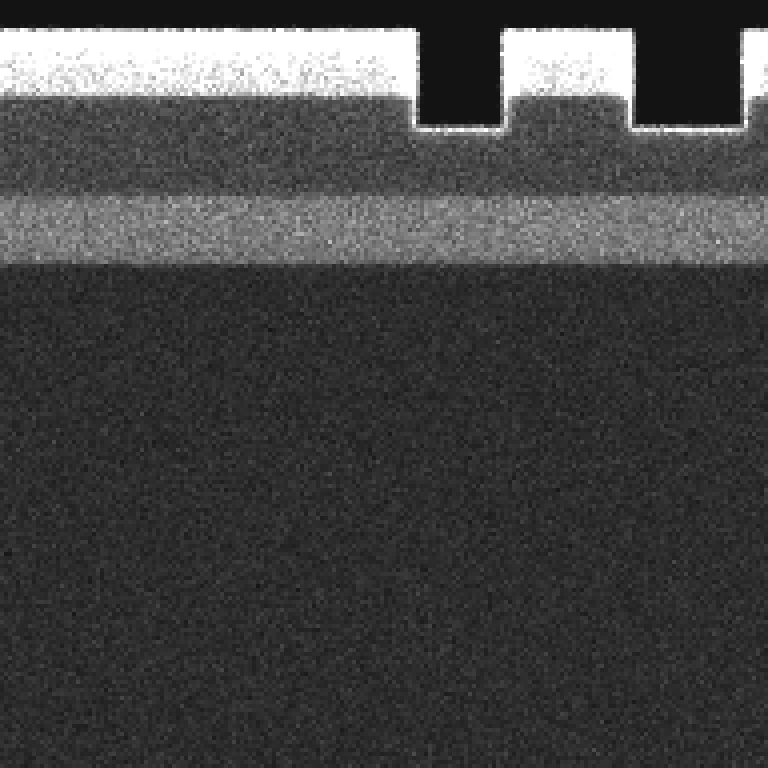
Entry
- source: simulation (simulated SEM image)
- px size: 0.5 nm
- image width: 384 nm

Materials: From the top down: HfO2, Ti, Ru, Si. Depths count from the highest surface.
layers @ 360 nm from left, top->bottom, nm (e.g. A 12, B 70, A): empty 48, Ti 34, Ru 34, Si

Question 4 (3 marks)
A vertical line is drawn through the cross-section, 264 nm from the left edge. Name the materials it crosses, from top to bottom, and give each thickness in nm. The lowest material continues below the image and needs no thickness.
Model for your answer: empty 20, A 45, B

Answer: HfO2 32, Ti 50, Ru 34, Si